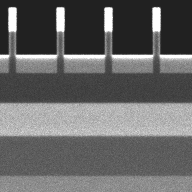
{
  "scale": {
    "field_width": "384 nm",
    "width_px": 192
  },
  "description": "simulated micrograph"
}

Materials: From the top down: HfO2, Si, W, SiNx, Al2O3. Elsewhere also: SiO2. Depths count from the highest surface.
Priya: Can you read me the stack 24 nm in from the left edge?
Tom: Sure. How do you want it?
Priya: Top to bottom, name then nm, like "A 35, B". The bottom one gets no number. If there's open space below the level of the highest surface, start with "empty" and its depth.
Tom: HfO2 46, Si 144, W 66, SiNx 80, Al2O3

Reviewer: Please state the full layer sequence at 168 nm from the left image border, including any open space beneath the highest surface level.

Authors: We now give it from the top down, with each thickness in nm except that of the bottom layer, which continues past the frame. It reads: empty 94, SiO2 36, Si 60, W 66, SiNx 80, Al2O3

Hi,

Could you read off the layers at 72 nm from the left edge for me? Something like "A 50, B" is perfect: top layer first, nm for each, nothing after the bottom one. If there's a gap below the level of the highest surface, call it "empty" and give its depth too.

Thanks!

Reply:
empty 94, SiO2 36, Si 60, W 66, SiNx 80, Al2O3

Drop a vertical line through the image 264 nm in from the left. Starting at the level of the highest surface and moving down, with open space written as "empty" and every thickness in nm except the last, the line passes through empty 94, SiO2 36, Si 60, W 66, SiNx 80, Al2O3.